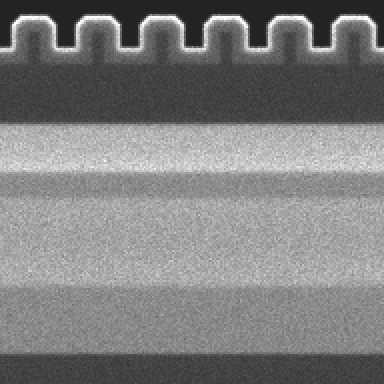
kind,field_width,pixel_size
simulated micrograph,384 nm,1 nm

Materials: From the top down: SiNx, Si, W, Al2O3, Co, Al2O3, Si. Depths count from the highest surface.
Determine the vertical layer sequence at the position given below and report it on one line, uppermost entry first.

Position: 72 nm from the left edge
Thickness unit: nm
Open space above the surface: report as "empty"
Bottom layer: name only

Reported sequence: empty 32, SiNx 16, Si 60, W 48, Al2O3 26, Co 88, Al2O3 68, Si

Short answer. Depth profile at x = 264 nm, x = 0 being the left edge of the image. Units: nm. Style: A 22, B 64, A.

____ empty 32, SiNx 16, Si 60, W 48, Al2O3 26, Co 88, Al2O3 68, Si